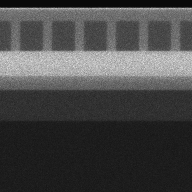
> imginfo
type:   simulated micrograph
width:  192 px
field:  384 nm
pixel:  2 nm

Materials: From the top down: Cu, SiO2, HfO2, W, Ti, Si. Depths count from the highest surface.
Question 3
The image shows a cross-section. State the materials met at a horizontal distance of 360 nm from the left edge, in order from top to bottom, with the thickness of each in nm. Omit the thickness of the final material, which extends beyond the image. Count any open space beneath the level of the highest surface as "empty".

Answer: Cu 26, SiO2 60, HfO2 50, W 28, Ti 62, Si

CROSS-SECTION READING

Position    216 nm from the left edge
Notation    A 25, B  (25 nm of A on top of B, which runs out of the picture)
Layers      Cu 86, HfO2 50, W 28, Ti 62, Si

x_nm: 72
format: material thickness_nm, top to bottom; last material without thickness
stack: Cu 26, SiO2 60, HfO2 50, W 28, Ti 62, Si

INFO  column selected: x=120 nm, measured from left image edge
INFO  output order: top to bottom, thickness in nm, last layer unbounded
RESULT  Cu 26, SiO2 60, HfO2 50, W 28, Ti 62, Si